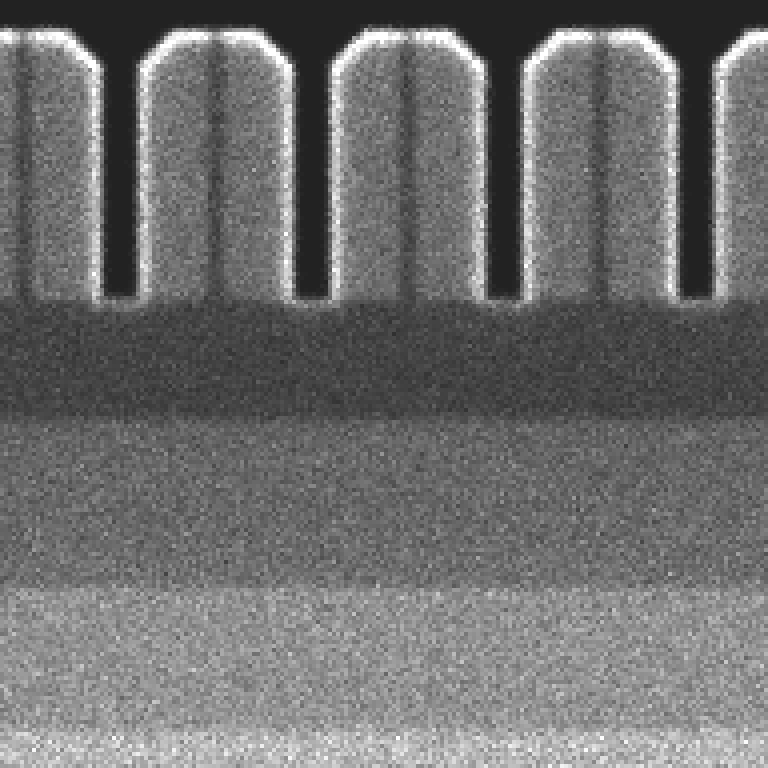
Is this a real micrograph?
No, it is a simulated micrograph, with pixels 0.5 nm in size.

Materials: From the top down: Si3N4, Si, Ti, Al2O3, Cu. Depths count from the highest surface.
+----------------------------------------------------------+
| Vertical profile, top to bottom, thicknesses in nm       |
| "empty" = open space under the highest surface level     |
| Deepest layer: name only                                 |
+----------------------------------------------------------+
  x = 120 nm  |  Si3N4 134, Si 60, Ti 84, Al2O3 72, Cu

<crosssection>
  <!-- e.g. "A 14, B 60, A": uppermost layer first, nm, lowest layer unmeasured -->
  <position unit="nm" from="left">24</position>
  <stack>Si3N4 134, Si 60, Ti 84, Al2O3 72, Cu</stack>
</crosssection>